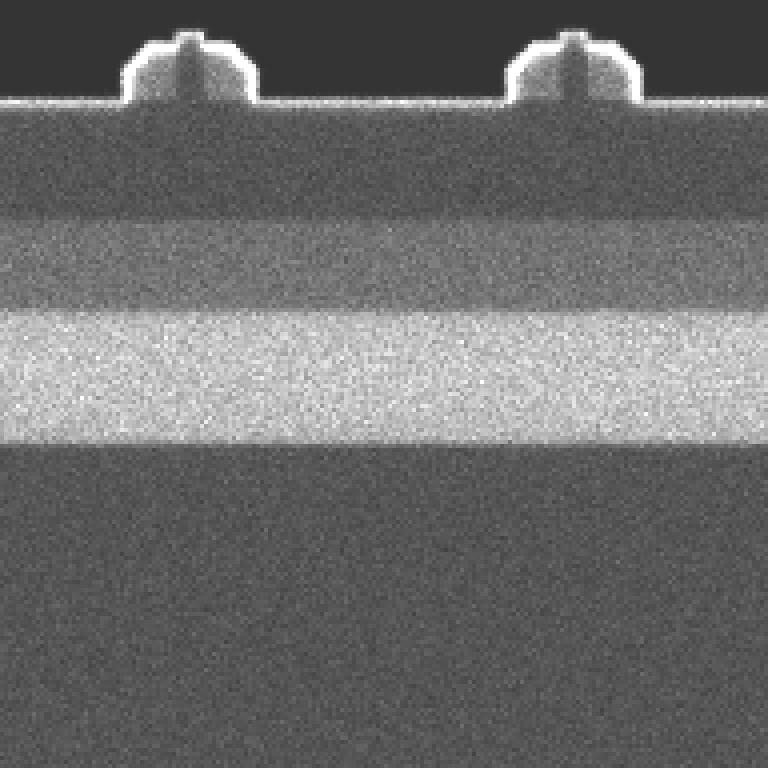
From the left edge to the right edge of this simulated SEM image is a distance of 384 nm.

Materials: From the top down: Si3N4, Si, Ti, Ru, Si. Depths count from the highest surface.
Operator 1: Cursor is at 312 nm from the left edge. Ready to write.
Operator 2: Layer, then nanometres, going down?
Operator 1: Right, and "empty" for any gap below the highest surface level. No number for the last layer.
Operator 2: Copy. empty 12, Si3N4 22, Si 60, Ti 46, Ru 66, Si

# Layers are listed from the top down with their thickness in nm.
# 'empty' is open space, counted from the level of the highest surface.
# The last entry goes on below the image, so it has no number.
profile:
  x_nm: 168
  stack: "empty 34, Si 60, Ti 46, Ru 66, Si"